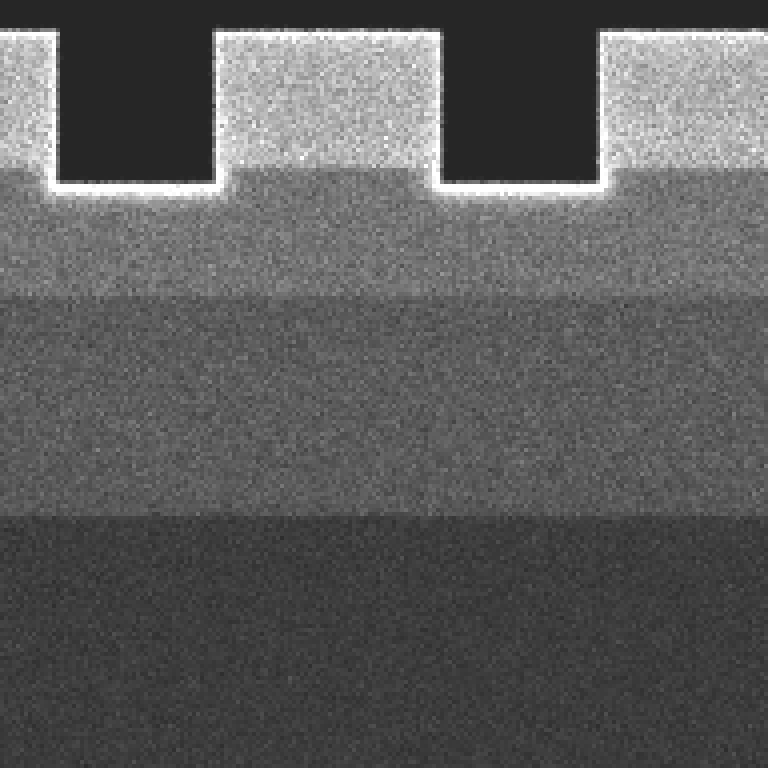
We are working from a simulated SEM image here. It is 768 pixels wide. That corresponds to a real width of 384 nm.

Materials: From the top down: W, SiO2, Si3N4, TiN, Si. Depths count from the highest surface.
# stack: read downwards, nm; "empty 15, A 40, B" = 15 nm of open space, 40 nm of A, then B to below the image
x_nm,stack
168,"W 68, SiO2 64, Si3N4 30, TiN 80, Si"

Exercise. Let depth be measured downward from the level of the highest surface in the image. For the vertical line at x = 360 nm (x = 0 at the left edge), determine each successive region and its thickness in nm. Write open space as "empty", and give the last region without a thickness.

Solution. W 68, SiO2 64, Si3N4 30, TiN 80, Si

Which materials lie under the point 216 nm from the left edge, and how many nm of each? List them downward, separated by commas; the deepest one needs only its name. W 68, SiO2 64, Si3N4 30, TiN 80, Si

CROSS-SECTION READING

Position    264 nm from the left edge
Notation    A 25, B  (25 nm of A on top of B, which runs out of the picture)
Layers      empty 76, SiO2 56, Si3N4 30, TiN 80, Si